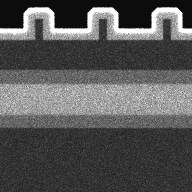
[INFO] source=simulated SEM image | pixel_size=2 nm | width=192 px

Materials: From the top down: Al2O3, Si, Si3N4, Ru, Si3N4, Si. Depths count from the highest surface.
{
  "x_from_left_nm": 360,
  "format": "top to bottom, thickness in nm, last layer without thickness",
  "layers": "empty 8, Al2O3 56, Si 60, Si3N4 28, Ru 62, Si3N4 26, Si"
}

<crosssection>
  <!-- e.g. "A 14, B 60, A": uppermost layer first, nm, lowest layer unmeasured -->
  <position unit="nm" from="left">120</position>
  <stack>empty 42, Al2O3 22, Si 60, Si3N4 28, Ru 62, Si3N4 26, Si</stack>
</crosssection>